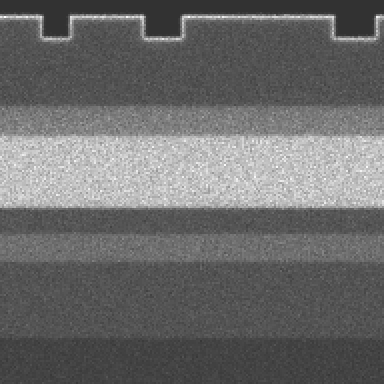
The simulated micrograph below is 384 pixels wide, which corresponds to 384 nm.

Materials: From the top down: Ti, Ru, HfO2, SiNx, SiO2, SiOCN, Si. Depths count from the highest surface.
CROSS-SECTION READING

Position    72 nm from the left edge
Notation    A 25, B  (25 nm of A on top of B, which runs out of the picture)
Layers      Ti 90, Ru 30, HfO2 72, SiNx 26, SiO2 28, SiOCN 76, Si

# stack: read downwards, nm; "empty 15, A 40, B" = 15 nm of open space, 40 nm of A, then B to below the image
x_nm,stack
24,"Ti 90, Ru 30, HfO2 72, SiNx 26, SiO2 28, SiOCN 76, Si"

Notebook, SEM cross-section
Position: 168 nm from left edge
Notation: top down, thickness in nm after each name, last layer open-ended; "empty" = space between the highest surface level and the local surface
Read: empty 22, Ti 68, Ru 30, HfO2 72, SiNx 26, SiO2 28, SiOCN 76, Si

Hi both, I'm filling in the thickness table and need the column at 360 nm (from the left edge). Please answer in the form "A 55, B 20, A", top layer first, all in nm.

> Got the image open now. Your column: empty 22, Ti 68, Ru 30, HfO2 72, SiNx 26, SiO2 28, SiOCN 76, Si